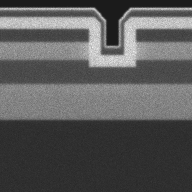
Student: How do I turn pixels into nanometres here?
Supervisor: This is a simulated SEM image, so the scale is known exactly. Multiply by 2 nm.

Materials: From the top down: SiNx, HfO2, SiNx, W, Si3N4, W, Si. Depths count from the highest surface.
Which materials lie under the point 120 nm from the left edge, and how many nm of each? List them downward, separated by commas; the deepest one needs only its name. SiNx 18, HfO2 24, SiNx 26, W 36, Si3N4 48, W 72, Si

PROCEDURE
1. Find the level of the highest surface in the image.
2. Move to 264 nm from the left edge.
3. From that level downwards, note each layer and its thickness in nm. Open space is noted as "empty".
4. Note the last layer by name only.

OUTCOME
SiNx 18, HfO2 100, Si3N4 34, W 72, Si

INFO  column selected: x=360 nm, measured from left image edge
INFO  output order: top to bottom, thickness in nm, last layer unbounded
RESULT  SiNx 18, HfO2 24, SiNx 26, W 36, Si3N4 48, W 72, Si